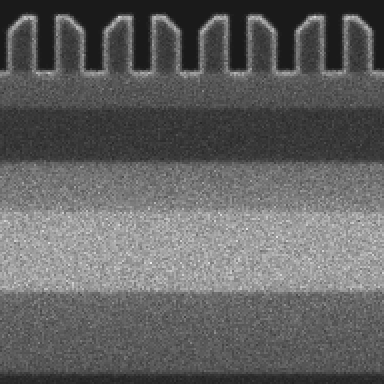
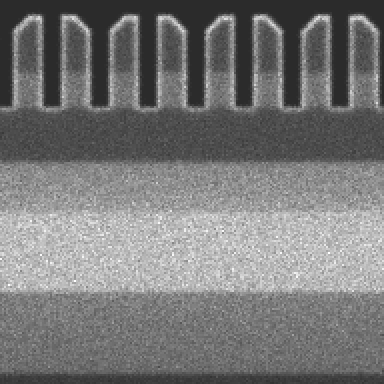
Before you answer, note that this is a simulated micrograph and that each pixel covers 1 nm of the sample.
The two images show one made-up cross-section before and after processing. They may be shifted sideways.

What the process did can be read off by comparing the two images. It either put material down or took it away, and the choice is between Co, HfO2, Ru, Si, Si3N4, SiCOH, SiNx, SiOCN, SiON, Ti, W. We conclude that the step removed Co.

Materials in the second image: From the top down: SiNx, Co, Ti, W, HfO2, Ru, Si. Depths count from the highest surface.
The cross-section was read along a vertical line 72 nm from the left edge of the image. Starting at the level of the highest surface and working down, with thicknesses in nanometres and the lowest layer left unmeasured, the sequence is SiNx 56, Co 36, Ti 54, W 50, HfO2 80, Ru 82, Si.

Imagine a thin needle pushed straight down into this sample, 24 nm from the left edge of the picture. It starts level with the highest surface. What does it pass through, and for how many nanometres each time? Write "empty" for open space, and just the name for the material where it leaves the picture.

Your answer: empty 4, SiNx 52, Co 36, Ti 54, W 50, HfO2 80, Ru 82, Si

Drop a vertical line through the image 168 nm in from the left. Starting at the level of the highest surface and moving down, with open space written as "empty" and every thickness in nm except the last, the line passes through SiNx 56, Co 36, Ti 54, W 50, HfO2 80, Ru 82, Si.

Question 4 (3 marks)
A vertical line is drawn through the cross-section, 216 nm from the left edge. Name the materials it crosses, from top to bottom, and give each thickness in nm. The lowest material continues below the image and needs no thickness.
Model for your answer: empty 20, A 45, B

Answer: empty 4, SiNx 52, Co 36, Ti 54, W 50, HfO2 80, Ru 82, Si